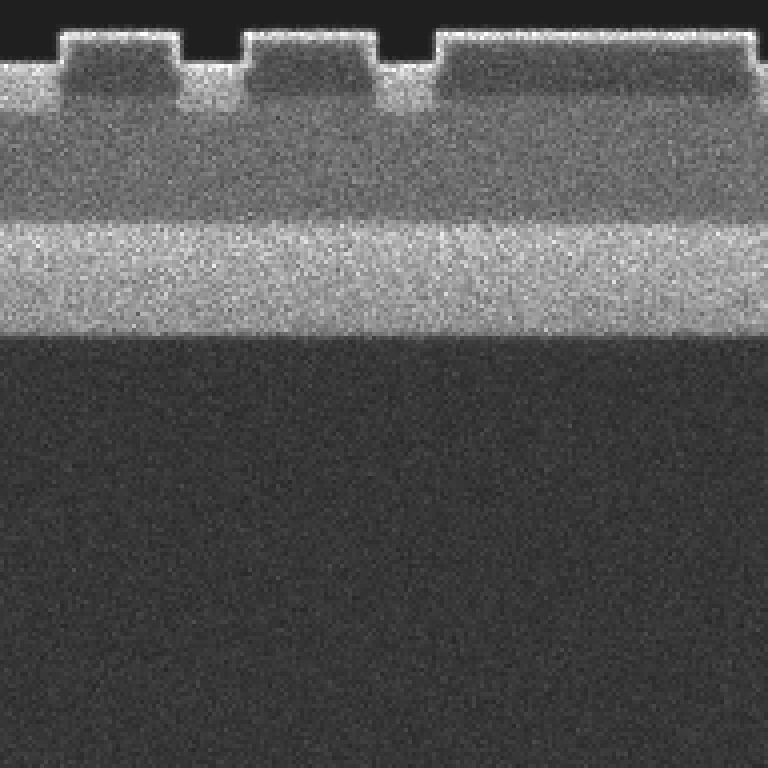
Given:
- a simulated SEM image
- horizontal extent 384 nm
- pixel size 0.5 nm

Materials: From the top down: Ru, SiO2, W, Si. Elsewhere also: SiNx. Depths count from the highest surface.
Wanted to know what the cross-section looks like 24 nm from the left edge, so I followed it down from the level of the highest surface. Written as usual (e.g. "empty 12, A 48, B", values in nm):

empty 16, Ru 24, SiO2 56, W 56, Si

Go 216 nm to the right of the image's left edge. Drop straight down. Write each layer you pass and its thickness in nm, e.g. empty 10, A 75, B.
empty 16, Ru 24, SiO2 56, W 56, Si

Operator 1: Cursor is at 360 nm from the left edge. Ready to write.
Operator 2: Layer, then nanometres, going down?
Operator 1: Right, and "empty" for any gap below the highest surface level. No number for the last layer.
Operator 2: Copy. SiNx 32, SiO2 64, W 56, Si